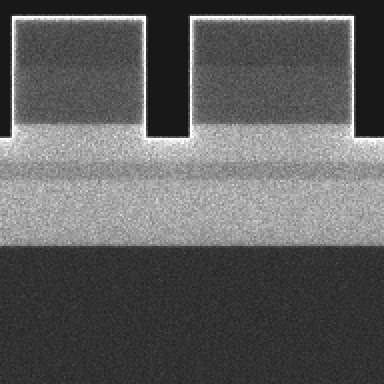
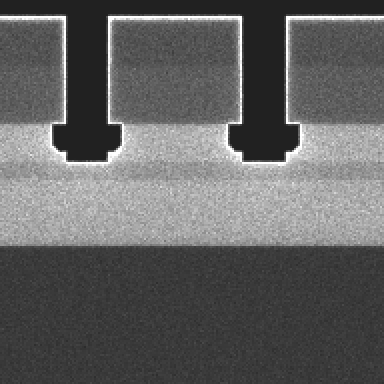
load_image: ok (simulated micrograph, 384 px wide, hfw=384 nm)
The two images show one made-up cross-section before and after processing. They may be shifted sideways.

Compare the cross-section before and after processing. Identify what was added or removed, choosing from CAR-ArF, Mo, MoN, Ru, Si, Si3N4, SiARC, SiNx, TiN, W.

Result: W removed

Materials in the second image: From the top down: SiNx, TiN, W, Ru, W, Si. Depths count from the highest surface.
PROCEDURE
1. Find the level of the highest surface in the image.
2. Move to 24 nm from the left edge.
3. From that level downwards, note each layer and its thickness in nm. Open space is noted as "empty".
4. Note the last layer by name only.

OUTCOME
SiNx 50, TiN 58, W 38, Ru 18, W 66, Si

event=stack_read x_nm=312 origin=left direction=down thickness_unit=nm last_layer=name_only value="SiNx 50, TiN 58, W 38, Ru 18, W 66, Si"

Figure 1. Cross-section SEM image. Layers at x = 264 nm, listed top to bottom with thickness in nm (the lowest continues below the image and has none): empty 146, Ru 18, W 66, Si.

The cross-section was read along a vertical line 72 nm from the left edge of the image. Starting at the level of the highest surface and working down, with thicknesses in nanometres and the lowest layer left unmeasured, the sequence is empty 146, Ru 18, W 66, Si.